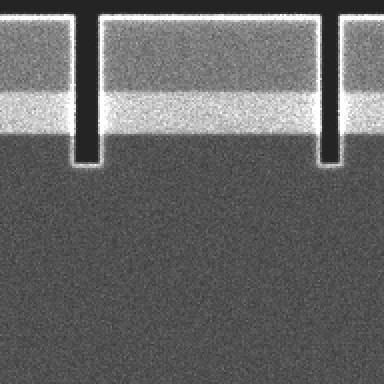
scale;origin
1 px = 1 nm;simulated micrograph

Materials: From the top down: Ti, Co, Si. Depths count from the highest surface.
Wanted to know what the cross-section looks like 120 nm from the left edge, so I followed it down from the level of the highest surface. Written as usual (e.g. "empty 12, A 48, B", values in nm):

Ti 76, Co 42, Si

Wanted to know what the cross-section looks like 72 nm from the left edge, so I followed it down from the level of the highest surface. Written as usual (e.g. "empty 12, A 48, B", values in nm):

Ti 76, Co 42, Si